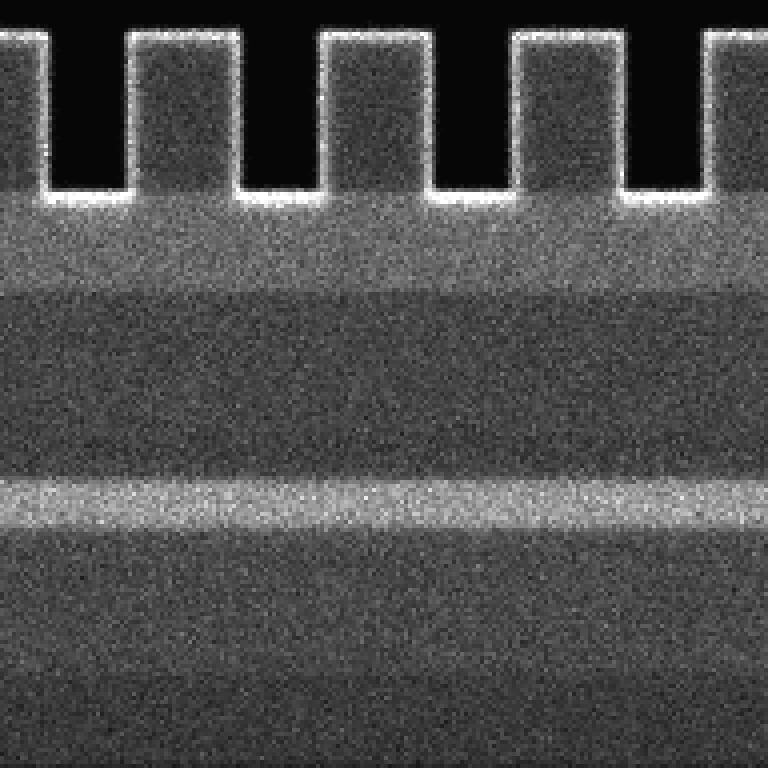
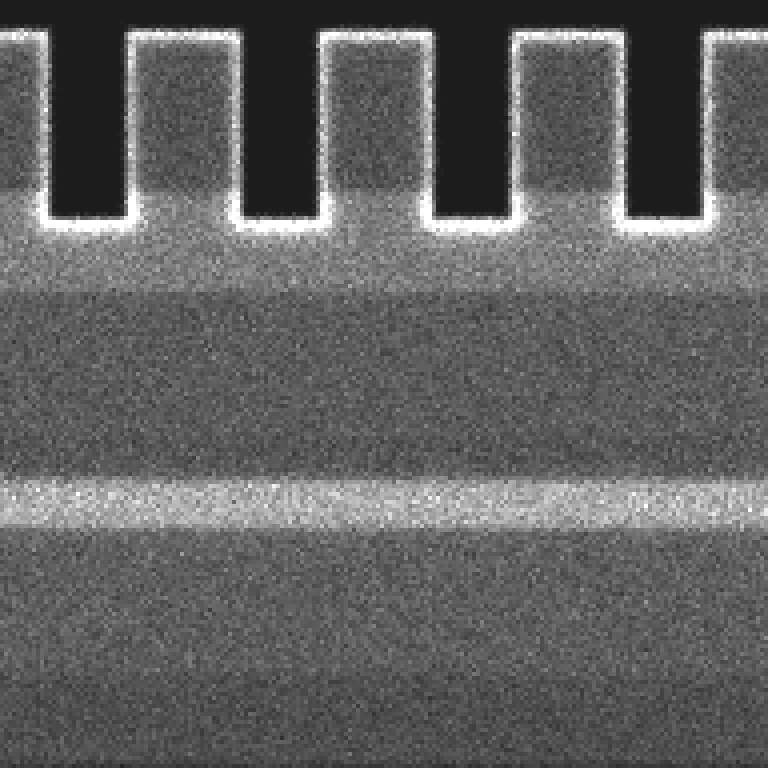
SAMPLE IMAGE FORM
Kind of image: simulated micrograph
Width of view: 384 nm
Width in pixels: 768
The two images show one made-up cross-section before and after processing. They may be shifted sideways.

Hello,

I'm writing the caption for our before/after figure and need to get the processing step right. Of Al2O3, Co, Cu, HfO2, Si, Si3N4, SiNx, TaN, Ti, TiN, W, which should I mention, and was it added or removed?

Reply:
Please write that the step removed Al2O3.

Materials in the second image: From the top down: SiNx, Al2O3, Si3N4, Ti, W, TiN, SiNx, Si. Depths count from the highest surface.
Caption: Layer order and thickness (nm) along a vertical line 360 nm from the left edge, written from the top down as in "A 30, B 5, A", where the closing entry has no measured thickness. SiNx 80, Al2O3 50, Si3N4 72, Ti 22, W 24, TiN 74, SiNx 44, Si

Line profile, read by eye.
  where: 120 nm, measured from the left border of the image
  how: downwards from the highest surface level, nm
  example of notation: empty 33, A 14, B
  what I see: empty 94, Al2O3 36, Si3N4 72, Ti 22, W 24, TiN 74, SiNx 44, Si